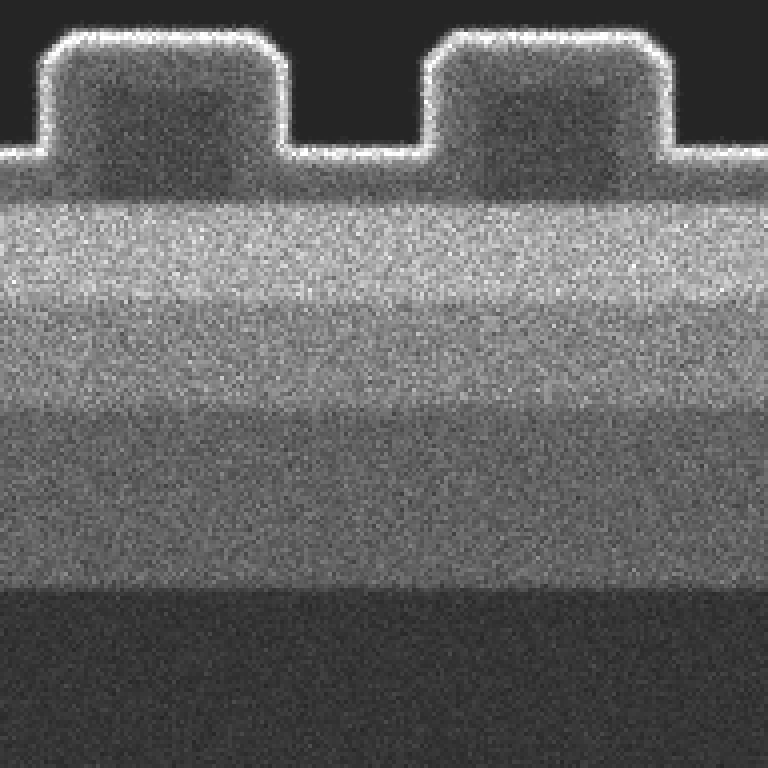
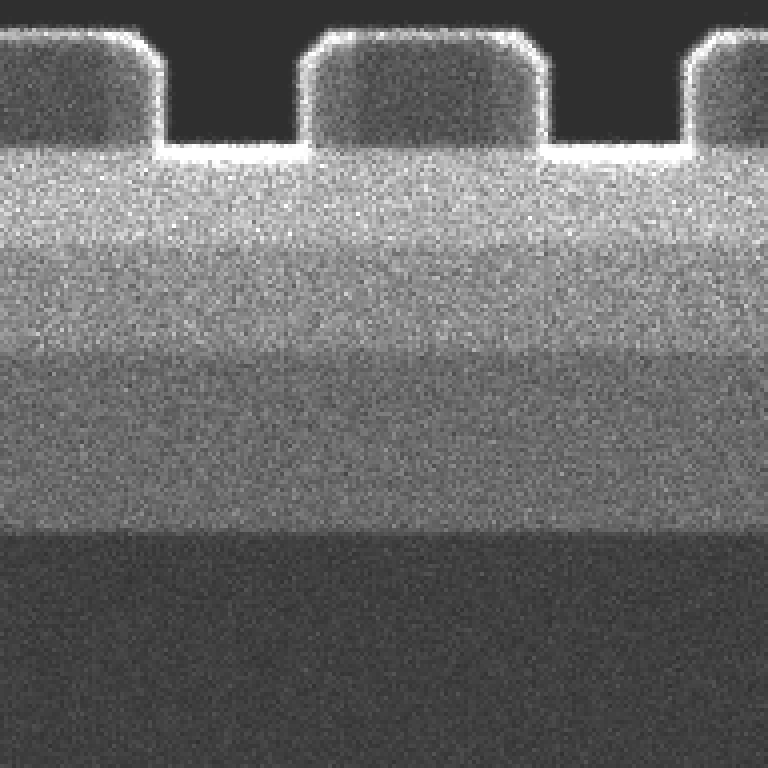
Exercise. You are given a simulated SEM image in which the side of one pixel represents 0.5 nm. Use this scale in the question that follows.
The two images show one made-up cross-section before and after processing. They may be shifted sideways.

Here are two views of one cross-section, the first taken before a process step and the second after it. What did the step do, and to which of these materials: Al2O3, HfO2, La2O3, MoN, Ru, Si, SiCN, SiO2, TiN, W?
It removed SiO2.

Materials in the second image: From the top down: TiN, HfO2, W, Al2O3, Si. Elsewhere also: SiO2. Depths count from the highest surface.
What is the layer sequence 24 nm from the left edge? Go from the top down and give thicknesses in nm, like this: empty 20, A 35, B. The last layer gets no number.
TiN 58, HfO2 48, W 54, Al2O3 90, Si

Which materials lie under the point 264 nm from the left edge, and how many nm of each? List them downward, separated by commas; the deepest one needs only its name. empty 6, SiO2 52, HfO2 48, W 54, Al2O3 90, Si